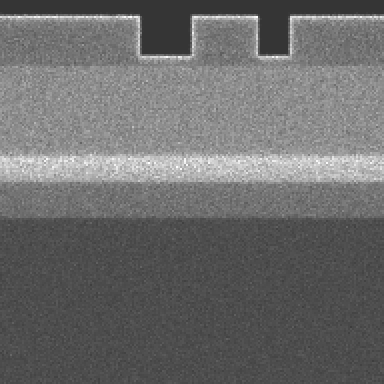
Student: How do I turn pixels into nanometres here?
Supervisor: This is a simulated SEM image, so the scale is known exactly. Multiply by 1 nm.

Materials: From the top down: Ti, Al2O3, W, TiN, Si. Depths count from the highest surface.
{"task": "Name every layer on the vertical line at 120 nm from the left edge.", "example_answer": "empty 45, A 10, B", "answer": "Ti 50, Al2O3 90, W 26, TiN 36, Si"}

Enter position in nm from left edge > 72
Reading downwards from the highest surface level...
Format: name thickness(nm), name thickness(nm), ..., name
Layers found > Ti 50, Al2O3 90, W 26, TiN 36, Si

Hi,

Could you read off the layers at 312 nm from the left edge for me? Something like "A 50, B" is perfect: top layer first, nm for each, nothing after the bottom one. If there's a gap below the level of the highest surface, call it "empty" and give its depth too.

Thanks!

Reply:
Ti 50, Al2O3 90, W 26, TiN 36, Si